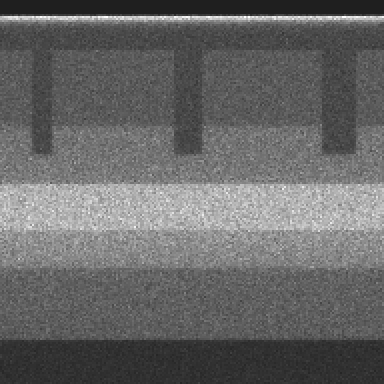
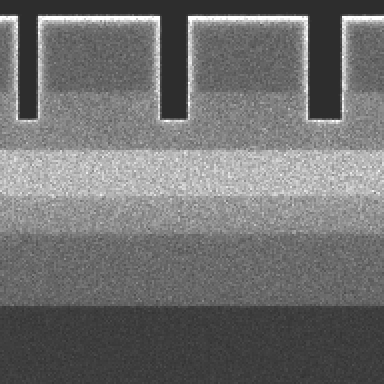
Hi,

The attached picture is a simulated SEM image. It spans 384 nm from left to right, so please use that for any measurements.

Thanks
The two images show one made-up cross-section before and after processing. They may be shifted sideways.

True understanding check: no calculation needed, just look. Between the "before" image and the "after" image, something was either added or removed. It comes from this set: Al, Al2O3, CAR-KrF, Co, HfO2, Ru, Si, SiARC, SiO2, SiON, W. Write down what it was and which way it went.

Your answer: SiARC (removed)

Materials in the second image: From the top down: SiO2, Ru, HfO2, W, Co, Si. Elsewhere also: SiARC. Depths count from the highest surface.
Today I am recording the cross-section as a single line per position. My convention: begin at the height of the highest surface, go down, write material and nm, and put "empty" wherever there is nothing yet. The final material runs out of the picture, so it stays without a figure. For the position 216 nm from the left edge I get SiO2 76, Ru 58, HfO2 46, W 38, Co 72, Si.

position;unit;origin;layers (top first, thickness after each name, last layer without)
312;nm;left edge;empty 104, Ru 30, HfO2 46, W 38, Co 72, Si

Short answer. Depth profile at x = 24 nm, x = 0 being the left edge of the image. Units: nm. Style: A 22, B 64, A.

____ empty 104, Ru 30, HfO2 46, W 38, Co 72, Si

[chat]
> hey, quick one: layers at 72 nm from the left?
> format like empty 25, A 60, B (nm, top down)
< SiO2 76, Ru 58, HfO2 46, W 38, Co 72, Si